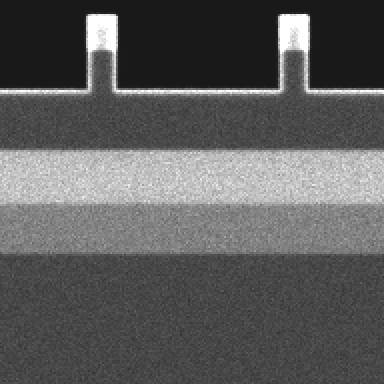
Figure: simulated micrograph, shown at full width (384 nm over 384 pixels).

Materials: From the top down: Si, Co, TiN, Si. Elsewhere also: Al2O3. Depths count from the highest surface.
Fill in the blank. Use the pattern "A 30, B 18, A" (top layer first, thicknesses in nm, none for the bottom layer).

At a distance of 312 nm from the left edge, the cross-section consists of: empty 74, Si 60, Co 54, TiN 50, Si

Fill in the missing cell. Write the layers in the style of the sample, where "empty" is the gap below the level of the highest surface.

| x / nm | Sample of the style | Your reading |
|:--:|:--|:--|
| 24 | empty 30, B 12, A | empty 74, Si 60, Co 54, TiN 50, Si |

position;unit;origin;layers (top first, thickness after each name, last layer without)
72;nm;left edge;empty 74, Si 60, Co 54, TiN 50, Si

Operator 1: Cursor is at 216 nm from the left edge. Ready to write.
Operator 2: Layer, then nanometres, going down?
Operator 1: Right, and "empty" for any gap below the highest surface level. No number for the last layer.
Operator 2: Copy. empty 74, Si 60, Co 54, TiN 50, Si